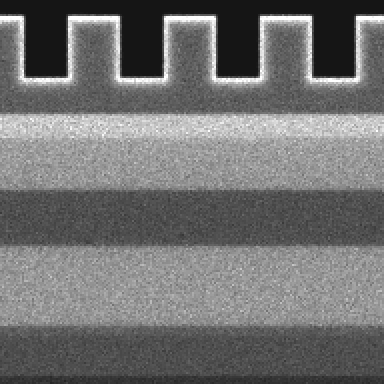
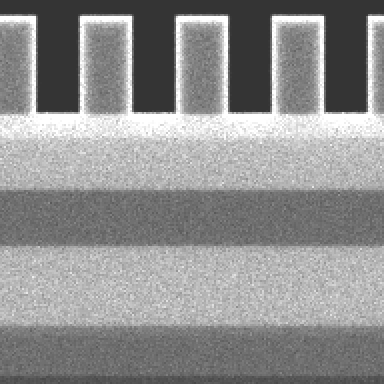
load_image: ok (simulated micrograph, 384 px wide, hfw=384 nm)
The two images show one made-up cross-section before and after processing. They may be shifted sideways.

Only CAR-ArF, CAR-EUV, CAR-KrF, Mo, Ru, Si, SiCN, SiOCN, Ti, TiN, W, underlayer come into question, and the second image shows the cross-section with underlayer removed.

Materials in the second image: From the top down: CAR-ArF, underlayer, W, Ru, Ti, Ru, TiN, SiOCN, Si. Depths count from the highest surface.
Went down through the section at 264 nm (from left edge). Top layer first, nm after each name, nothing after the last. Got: empty 98, W 24, Ru 52, Ti 56, Ru 80, TiN 10, SiOCN 40, Si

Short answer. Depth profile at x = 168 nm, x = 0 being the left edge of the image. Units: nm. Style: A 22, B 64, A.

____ empty 98, W 24, Ru 52, Ti 56, Ru 80, TiN 10, SiOCN 40, Si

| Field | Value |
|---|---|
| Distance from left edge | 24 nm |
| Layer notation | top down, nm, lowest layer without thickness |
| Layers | CAR-ArF 62, underlayer 36, W 24, Ru 52, Ti 56, Ru 80, TiN 10, SiOCN 40, Si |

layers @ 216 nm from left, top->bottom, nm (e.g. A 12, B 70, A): CAR-ArF 62, underlayer 36, W 24, Ru 52, Ti 56, Ru 80, TiN 10, SiOCN 40, Si